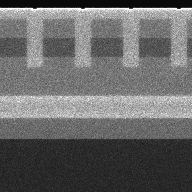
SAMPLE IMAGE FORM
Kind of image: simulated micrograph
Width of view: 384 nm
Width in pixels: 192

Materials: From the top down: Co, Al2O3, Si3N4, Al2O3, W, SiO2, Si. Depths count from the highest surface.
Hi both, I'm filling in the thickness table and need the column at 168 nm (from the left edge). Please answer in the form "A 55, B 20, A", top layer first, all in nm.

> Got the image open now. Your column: empty 2, Co 116, Al2O3 58, W 44, SiO2 42, Si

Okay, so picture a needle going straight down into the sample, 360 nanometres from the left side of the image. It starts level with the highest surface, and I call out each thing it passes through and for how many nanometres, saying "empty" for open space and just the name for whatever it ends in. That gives empty 2, Co 116, Al2O3 58, W 44, SiO2 42, Si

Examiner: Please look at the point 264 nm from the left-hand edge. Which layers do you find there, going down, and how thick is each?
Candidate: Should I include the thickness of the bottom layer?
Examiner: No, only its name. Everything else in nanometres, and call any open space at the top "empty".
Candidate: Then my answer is empty 2, Co 116, Al2O3 58, W 44, SiO2 42, Si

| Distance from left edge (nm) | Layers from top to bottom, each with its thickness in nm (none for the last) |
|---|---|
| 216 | Co 22, Al2O3 38, Si3N4 38, Al2O3 78, W 44, SiO2 42, Si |